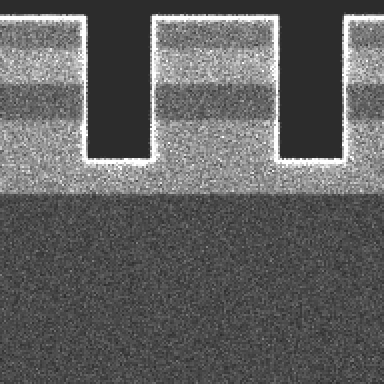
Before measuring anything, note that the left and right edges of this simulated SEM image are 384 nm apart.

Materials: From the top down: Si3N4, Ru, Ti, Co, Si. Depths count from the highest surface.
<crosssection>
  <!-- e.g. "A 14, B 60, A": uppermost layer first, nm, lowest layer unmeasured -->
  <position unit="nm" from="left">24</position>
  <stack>Si3N4 32, Ru 36, Ti 36, Co 74, Si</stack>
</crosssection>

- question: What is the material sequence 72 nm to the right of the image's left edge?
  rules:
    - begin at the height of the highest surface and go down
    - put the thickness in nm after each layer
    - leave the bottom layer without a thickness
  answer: Si3N4 32, Ru 36, Ti 36, Co 74, Si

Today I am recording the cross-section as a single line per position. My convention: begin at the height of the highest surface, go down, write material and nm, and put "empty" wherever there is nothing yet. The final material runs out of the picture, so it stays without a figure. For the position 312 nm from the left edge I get empty 144, Co 34, Si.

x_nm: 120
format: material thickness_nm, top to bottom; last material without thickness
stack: empty 144, Co 34, Si